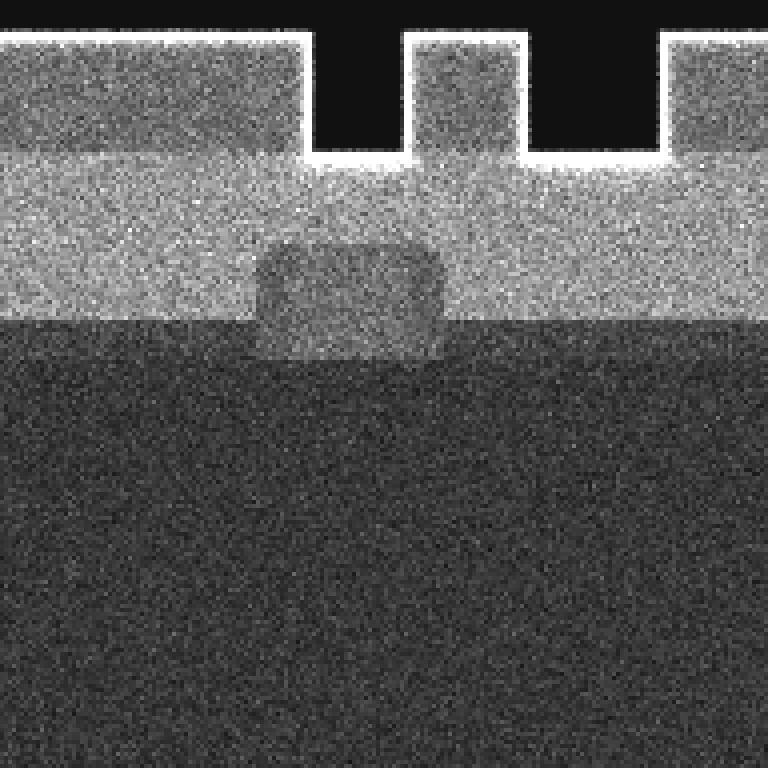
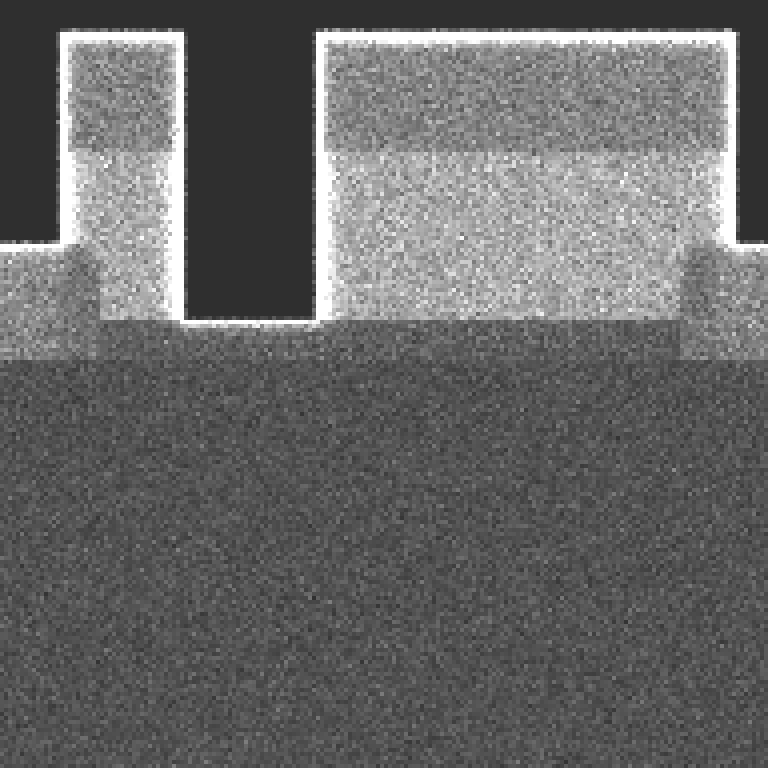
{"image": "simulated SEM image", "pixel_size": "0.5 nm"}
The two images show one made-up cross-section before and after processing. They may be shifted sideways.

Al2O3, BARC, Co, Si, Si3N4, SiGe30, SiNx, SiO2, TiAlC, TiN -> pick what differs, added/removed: SiO2 removed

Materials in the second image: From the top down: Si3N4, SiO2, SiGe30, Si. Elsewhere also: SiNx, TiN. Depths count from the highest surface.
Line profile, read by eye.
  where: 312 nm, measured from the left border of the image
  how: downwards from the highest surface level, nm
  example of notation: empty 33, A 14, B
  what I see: Si3N4 60, SiO2 84, SiGe30 20, Si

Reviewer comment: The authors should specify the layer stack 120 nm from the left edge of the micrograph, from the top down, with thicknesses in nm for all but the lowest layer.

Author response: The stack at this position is empty 144, SiGe30 20, Si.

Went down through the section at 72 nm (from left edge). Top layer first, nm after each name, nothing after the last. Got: Si3N4 60, SiO2 84, SiGe30 20, Si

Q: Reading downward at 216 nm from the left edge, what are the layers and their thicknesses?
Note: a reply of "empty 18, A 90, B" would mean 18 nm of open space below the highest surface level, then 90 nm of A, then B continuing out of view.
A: Si3N4 60, SiO2 84, SiGe30 20, Si